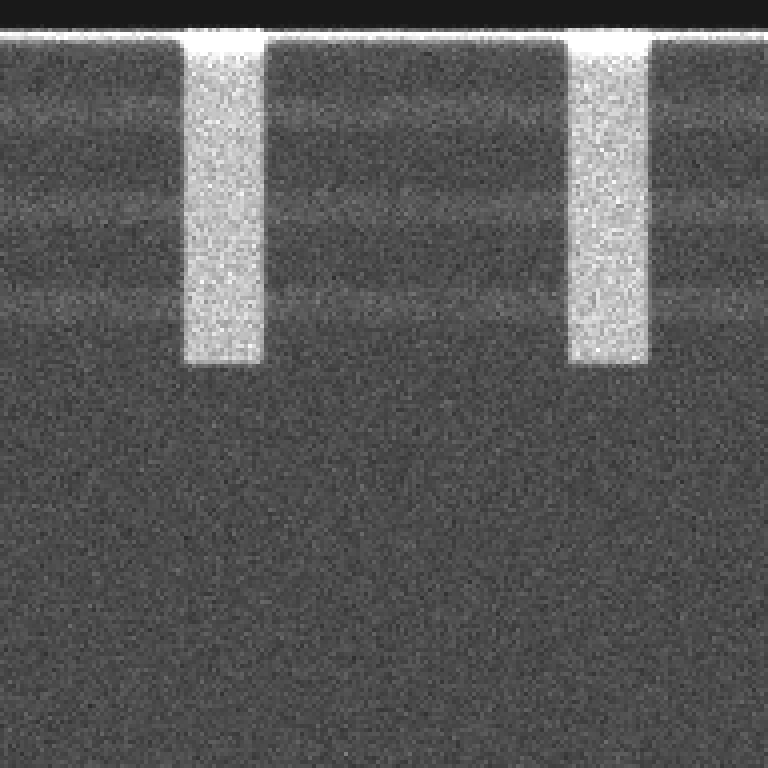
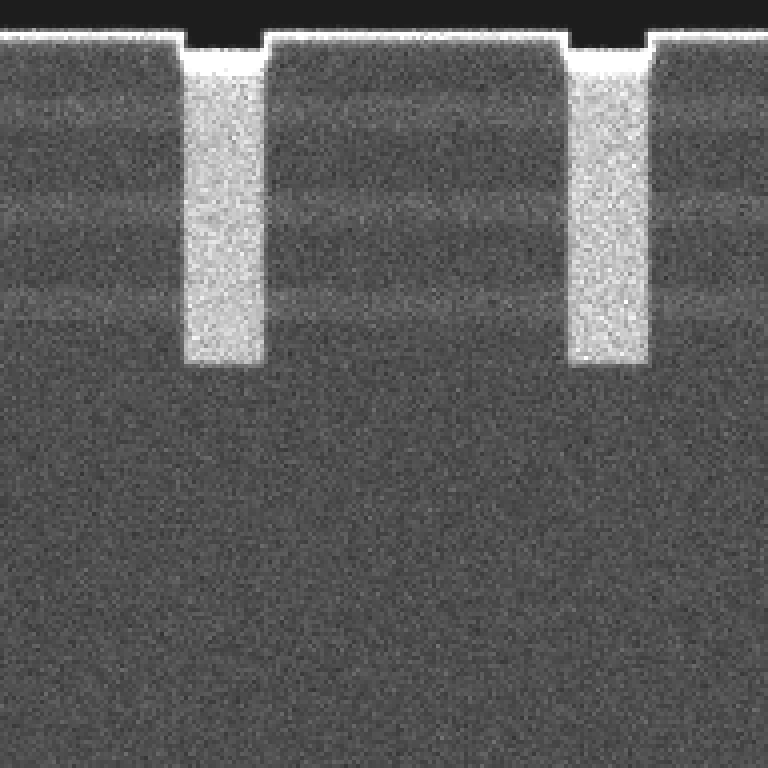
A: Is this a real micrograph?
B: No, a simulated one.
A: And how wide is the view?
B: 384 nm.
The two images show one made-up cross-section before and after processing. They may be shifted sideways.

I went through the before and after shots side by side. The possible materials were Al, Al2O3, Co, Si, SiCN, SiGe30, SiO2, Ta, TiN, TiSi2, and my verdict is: removed, SiO2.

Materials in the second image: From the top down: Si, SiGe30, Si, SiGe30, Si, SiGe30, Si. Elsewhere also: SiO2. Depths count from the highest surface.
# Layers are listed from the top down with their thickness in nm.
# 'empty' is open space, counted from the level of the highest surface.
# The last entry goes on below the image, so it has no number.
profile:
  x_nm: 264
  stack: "Si 32, SiGe30 16, Si 32, SiGe30 16, Si 32, SiGe30 16, Si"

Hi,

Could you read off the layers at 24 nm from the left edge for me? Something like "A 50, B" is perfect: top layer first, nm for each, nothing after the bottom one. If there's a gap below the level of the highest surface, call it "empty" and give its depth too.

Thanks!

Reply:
Si 32, SiGe30 16, Si 32, SiGe30 16, Si 32, SiGe30 16, Si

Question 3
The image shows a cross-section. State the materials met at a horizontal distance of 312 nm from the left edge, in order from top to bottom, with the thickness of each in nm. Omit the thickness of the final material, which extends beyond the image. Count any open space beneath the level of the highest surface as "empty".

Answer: empty 10, SiO2 156, Si